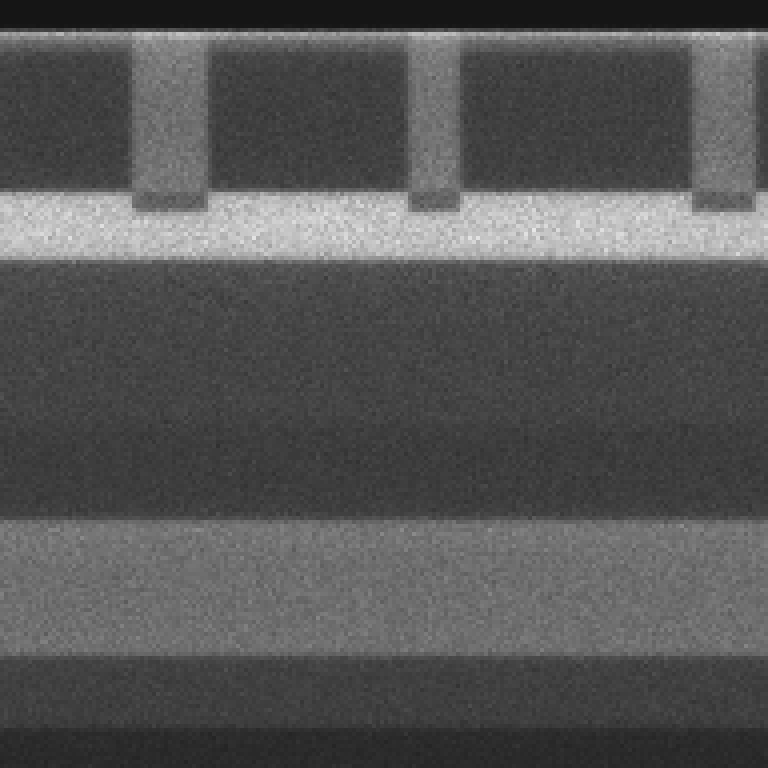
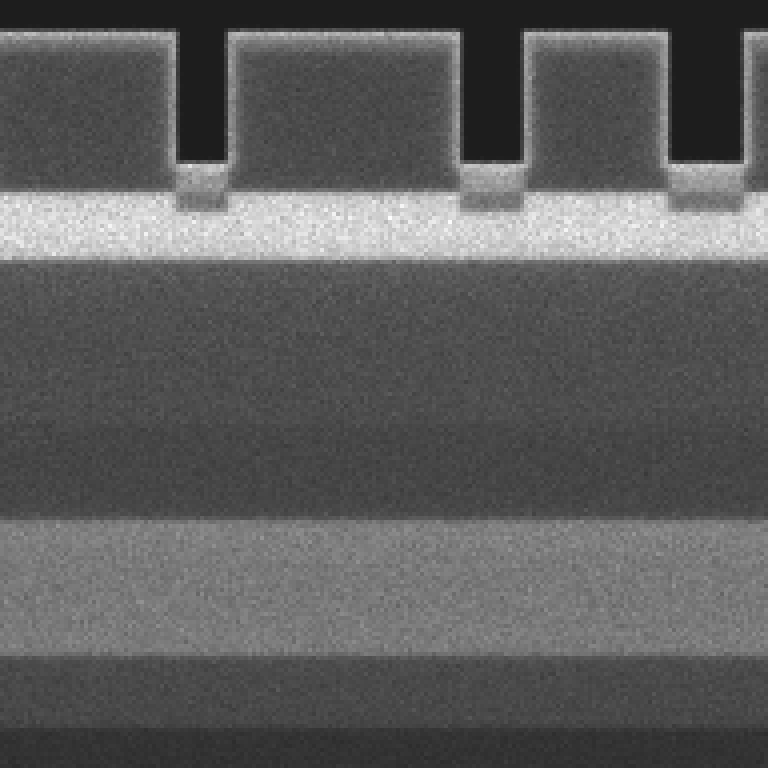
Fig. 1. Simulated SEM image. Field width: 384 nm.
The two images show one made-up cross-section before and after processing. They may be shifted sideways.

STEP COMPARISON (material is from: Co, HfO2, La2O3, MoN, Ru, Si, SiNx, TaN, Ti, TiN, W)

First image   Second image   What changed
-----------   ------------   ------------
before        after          Co, removed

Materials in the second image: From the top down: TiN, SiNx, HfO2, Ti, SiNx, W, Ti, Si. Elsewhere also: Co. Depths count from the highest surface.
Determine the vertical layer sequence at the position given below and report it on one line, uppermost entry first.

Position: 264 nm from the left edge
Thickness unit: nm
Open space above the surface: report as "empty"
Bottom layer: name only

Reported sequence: TiN 10, SiNx 70, HfO2 34, Ti 82, SiNx 48, W 68, Ti 36, Si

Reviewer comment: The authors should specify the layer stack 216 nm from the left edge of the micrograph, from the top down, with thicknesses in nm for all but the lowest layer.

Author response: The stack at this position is TiN 10, SiNx 70, HfO2 34, Ti 82, SiNx 48, W 68, Ti 36, Si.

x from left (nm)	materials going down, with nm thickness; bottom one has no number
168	TiN 10, SiNx 70, HfO2 34, Ti 82, SiNx 48, W 68, Ti 36, Si